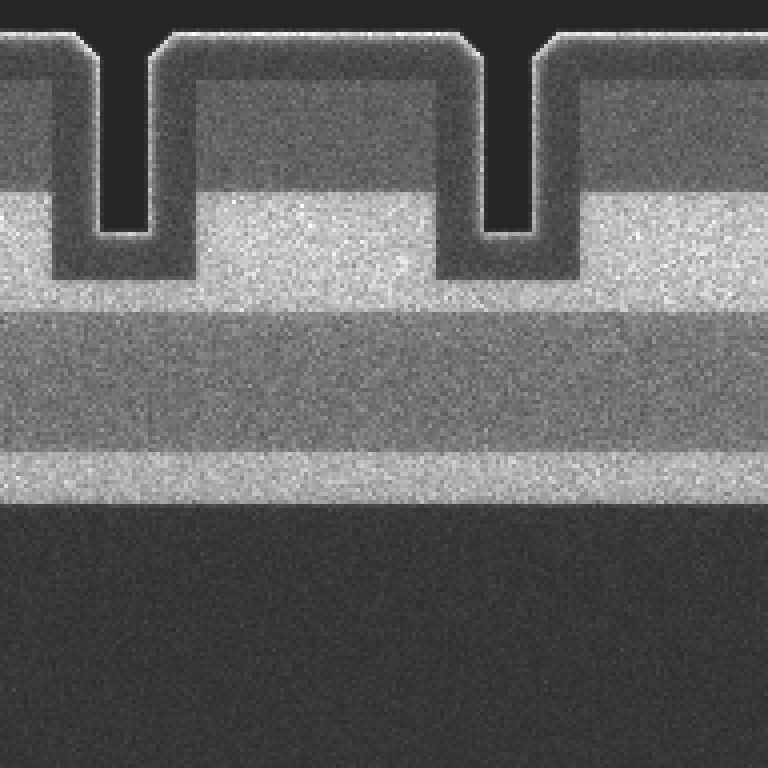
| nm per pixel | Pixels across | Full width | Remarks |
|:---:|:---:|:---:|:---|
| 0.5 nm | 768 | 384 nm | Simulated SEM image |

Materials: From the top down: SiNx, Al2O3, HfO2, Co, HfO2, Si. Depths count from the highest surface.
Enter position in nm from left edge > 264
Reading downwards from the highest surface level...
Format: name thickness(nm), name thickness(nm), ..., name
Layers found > empty 100, SiNx 24, HfO2 16, Co 70, HfO2 26, Si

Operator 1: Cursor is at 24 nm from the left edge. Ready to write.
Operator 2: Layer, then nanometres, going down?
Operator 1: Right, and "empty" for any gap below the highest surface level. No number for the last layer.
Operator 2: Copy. SiNx 24, Al2O3 56, HfO2 60, Co 70, HfO2 26, Si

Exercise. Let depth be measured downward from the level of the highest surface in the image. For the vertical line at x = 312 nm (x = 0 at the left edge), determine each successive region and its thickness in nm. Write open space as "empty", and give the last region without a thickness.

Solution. SiNx 24, Al2O3 56, HfO2 60, Co 70, HfO2 26, Si